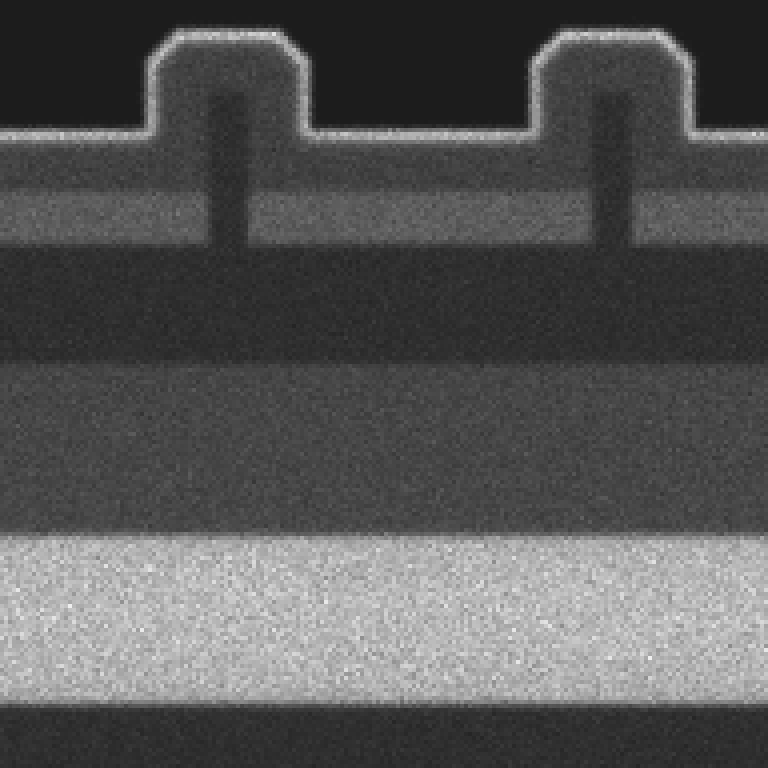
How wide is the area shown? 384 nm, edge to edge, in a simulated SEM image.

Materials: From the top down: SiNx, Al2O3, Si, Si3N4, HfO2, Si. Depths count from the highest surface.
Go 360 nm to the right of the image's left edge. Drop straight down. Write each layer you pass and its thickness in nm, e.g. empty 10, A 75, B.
empty 50, SiNx 30, Al2O3 26, Si 60, Si3N4 86, HfO2 84, Si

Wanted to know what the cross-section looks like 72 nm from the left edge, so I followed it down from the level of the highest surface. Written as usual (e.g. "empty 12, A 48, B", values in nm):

empty 50, SiNx 30, Al2O3 26, Si 60, Si3N4 86, HfO2 84, Si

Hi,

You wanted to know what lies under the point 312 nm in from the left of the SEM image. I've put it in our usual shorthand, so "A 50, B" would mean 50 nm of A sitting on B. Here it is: SiNx 30, Si 136, Si3N4 86, HfO2 84, Si